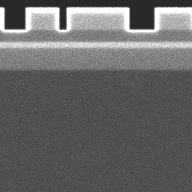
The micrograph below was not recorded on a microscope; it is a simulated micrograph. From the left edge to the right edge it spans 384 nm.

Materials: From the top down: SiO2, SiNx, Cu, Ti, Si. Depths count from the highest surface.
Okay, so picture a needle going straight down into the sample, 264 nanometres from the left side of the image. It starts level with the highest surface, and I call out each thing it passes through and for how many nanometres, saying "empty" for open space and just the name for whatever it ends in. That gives empty 44, SiNx 24, Cu 12, Ti 44, Si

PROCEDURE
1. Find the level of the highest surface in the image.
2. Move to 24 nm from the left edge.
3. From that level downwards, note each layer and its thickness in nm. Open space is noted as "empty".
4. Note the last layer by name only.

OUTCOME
empty 44, SiNx 24, Cu 12, Ti 44, Si